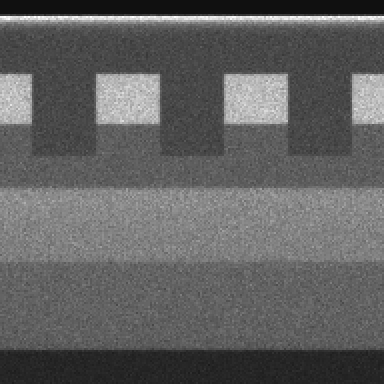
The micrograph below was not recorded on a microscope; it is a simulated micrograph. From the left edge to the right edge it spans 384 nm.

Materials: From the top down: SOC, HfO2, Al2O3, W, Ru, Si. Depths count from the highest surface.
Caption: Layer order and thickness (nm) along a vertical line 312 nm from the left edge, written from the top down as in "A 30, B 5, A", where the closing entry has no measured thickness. SOC 140, Al2O3 32, W 74, Ru 88, Si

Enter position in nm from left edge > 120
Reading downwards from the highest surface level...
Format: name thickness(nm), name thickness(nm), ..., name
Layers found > SOC 58, HfO2 50, Al2O3 64, W 74, Ru 88, Si